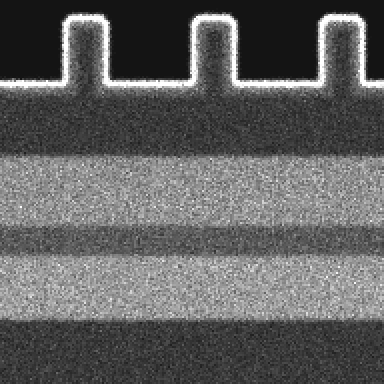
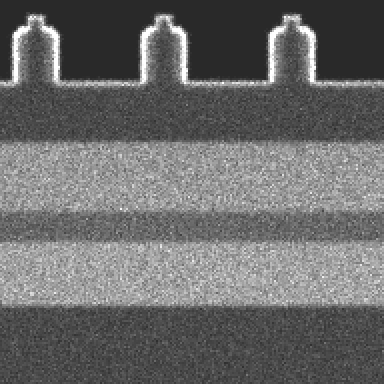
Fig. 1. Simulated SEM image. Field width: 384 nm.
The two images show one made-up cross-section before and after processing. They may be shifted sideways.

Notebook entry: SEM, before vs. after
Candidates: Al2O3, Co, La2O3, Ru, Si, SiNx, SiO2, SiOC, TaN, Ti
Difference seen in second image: SiNx removed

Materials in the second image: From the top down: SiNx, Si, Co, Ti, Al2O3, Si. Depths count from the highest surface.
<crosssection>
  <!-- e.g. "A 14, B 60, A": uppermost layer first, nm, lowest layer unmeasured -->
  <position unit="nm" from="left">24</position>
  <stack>empty 12, SiNx 54, Si 60, Co 70, Ti 30, Al2O3 64, Si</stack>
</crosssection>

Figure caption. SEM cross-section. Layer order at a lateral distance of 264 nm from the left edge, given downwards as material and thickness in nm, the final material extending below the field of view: empty 66, Si 60, Co 70, Ti 30, Al2O3 64, Si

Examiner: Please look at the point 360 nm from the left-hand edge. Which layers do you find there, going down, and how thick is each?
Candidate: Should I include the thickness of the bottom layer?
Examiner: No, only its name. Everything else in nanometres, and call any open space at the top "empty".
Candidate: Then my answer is empty 66, Si 60, Co 70, Ti 30, Al2O3 64, Si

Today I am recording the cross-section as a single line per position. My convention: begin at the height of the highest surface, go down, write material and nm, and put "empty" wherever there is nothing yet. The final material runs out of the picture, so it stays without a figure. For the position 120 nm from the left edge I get empty 66, Si 60, Co 70, Ti 30, Al2O3 64, Si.